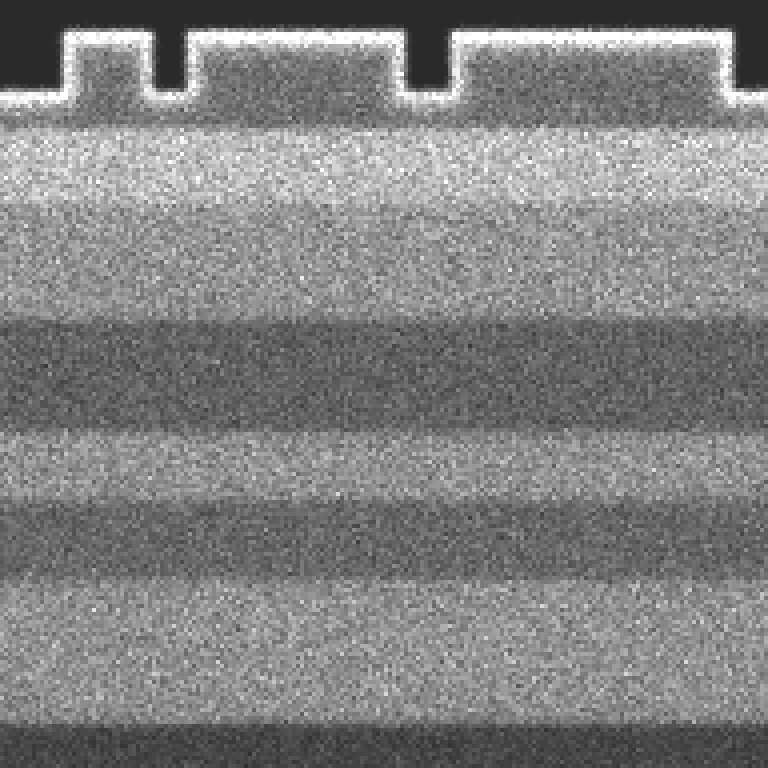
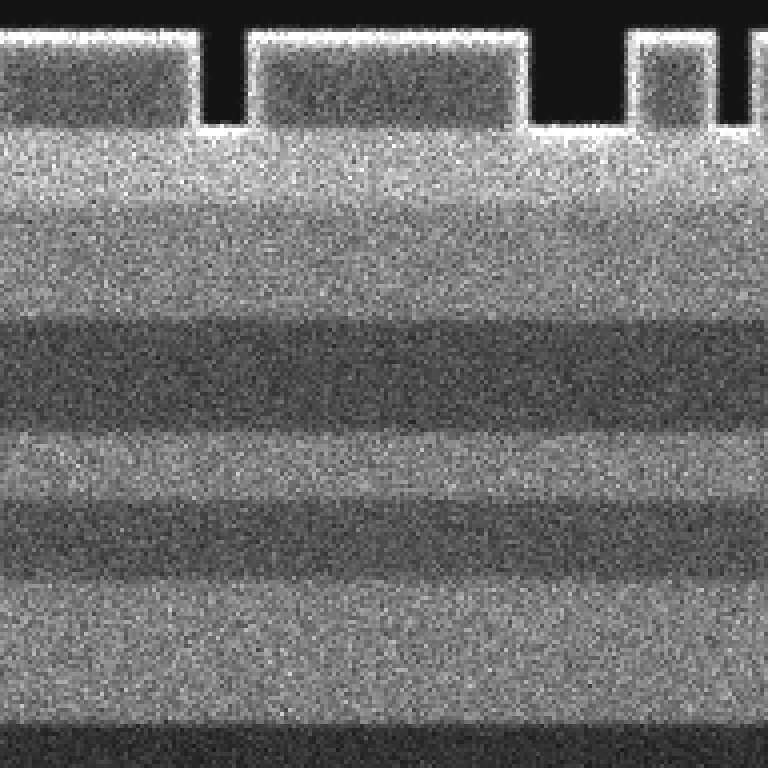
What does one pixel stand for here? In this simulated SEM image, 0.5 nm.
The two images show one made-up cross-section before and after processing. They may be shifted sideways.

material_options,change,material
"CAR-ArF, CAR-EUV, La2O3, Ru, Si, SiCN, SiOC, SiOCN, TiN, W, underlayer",removed,underlayer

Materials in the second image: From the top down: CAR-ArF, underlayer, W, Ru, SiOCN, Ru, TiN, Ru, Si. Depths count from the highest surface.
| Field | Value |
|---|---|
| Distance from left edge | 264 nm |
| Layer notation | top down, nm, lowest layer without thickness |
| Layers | empty 48, W 38, Ru 58, SiOCN 56, Ru 34, TiN 40, Ru 72, Si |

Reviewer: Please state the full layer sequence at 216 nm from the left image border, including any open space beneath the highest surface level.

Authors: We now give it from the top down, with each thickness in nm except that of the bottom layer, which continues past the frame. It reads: CAR-ArF 30, underlayer 18, W 38, Ru 58, SiOCN 56, Ru 34, TiN 40, Ru 72, Si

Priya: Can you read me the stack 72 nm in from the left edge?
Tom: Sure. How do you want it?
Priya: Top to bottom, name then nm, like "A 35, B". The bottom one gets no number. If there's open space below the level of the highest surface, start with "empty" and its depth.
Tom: CAR-ArF 30, underlayer 18, W 38, Ru 58, SiOCN 56, Ru 34, TiN 40, Ru 72, Si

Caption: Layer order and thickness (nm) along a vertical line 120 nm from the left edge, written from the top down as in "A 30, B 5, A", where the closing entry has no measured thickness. empty 48, W 38, Ru 58, SiOCN 56, Ru 34, TiN 40, Ru 72, Si